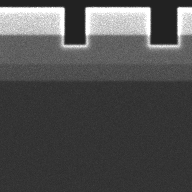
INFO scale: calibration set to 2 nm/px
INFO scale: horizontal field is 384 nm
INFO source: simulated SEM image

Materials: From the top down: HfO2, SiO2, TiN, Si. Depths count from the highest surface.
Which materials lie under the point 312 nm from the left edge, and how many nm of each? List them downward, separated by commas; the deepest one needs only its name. empty 74, SiO2 38, TiN 34, Si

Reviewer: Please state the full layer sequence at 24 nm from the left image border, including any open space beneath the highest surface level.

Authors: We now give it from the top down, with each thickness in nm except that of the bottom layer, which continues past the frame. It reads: HfO2 54, SiO2 58, TiN 34, Si